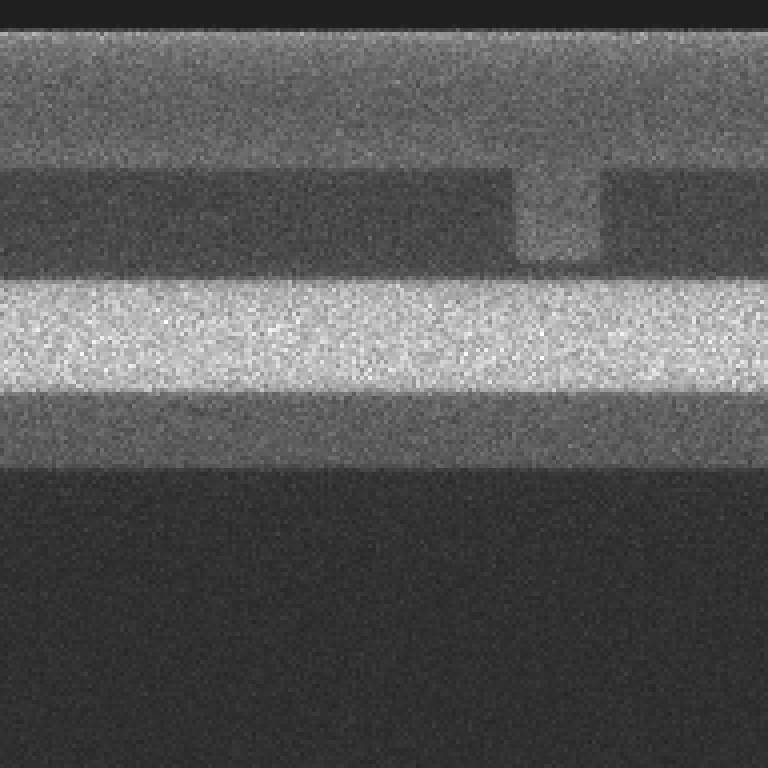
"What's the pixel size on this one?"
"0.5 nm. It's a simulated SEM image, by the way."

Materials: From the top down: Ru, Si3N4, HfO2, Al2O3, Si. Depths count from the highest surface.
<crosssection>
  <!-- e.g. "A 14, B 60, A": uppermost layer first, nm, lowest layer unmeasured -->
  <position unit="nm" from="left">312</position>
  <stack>Ru 68, Si3N4 56, HfO2 56, Al2O3 38, Si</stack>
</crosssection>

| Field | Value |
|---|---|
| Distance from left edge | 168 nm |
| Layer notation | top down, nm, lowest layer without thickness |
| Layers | Ru 68, Si3N4 56, HfO2 56, Al2O3 38, Si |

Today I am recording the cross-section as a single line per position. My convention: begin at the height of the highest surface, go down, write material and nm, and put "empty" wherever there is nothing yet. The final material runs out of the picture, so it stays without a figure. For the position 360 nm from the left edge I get Ru 68, Si3N4 56, HfO2 56, Al2O3 38, Si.